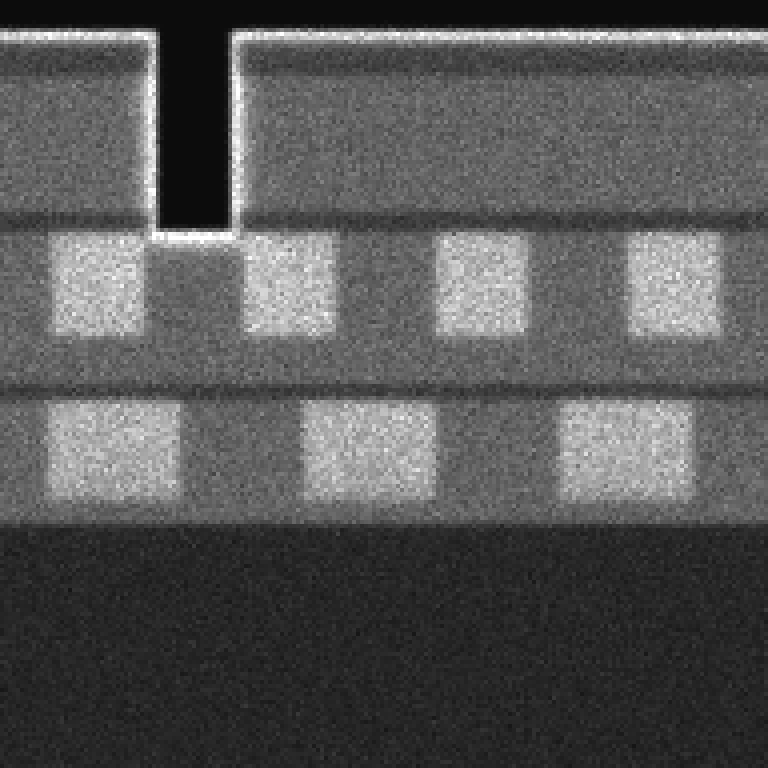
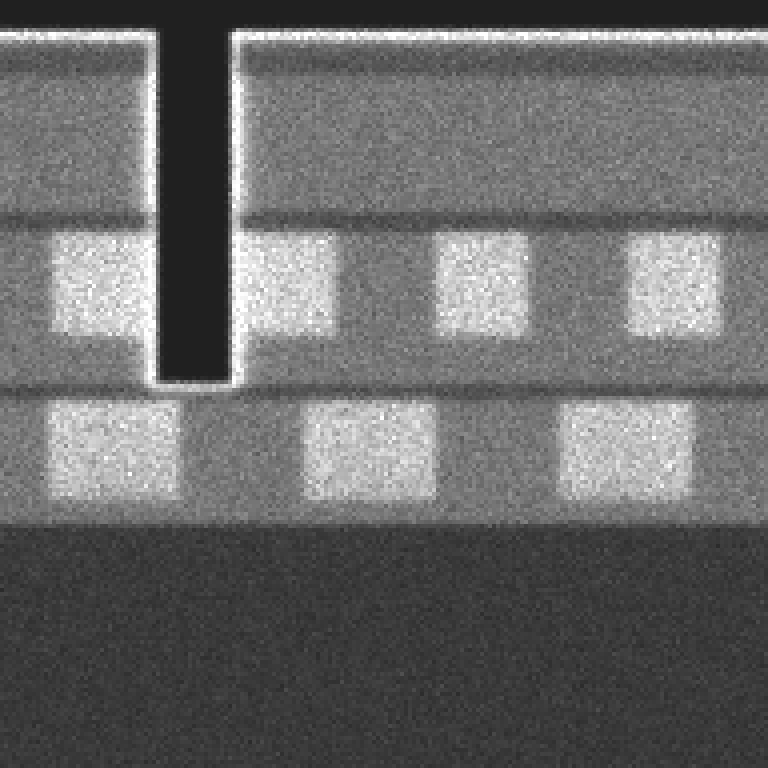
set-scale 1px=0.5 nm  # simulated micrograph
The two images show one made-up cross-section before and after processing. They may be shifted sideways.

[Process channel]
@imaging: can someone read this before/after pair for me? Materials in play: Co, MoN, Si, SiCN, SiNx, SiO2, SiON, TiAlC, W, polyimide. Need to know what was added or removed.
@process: SiO2 removed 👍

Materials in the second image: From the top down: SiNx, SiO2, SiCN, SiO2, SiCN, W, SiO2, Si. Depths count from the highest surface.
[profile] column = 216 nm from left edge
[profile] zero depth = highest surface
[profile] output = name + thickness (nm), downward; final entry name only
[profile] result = SiNx 22, SiO2 68, SiCN 10, SiO2 76, SiCN 8, W 50, SiO2 12, Si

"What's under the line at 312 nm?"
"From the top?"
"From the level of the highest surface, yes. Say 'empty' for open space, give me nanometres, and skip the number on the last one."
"SiNx 22, SiO2 68, SiCN 10, SiO2 76, SiCN 8, W 50, SiO2 12, Si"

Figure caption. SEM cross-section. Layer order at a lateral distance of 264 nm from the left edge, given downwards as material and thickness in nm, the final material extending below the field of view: SiNx 22, SiO2 68, SiCN 10, SiO2 76, SiCN 8, SiO2 62, Si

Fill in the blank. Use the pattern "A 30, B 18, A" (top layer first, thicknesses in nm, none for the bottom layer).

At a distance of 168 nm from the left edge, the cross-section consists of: SiNx 22, SiO2 68, SiCN 10, SiO2 76, SiCN 8, W 50, SiO2 12, Si